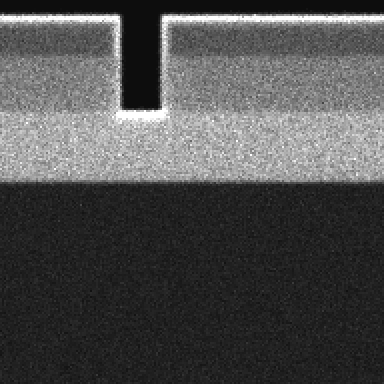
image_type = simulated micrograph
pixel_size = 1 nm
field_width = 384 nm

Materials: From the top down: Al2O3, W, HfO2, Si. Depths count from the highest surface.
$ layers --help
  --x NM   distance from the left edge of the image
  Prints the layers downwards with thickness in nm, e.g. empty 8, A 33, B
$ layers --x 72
Al2O3 40, W 56, HfO2 70, Si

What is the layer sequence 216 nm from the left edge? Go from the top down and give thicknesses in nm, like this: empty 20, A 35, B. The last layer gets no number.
Al2O3 40, W 56, HfO2 70, Si